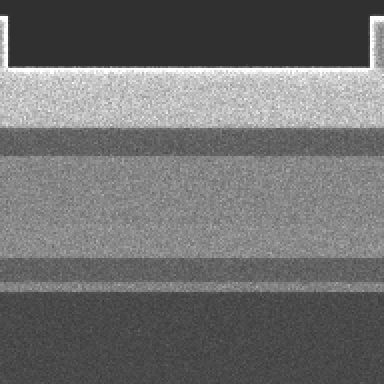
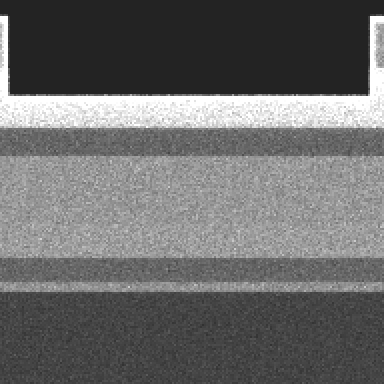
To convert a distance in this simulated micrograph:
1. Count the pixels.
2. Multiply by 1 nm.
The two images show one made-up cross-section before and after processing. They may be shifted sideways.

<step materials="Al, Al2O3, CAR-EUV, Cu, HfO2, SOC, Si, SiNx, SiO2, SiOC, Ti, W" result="removed W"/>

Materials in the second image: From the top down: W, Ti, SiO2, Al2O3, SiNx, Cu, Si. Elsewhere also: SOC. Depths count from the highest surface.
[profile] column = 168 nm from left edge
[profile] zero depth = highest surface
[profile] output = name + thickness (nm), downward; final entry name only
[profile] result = empty 80, W 32, Ti 28, SiO2 68, Al2O3 34, SiNx 24, Cu 10, Si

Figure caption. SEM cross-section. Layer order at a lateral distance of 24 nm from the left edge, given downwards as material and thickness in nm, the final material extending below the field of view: empty 80, W 32, Ti 28, SiO2 68, Al2O3 34, SiNx 24, Cu 10, Si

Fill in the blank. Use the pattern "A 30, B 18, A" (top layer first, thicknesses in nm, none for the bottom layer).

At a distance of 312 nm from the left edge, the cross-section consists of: empty 80, W 32, Ti 28, SiO2 68, Al2O3 34, SiNx 24, Cu 10, Si